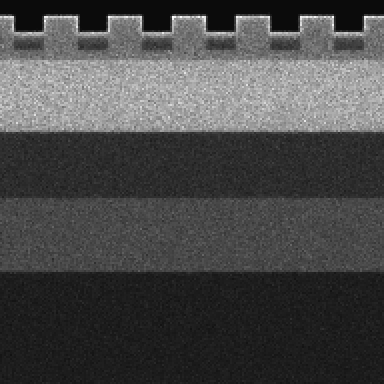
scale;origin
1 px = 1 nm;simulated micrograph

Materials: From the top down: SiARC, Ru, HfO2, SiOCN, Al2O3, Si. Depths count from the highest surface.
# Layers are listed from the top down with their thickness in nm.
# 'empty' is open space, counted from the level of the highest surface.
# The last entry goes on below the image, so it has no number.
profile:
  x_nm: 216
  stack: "empty 16, SiARC 18, Ru 10, HfO2 72, SiOCN 66, Al2O3 74, Si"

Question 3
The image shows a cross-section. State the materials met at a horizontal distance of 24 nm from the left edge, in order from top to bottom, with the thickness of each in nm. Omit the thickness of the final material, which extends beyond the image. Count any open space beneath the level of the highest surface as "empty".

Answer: empty 16, SiARC 18, Ru 10, HfO2 72, SiOCN 66, Al2O3 74, Si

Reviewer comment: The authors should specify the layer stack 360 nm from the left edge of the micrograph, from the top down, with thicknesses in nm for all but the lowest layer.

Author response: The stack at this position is empty 16, SiARC 18, Ru 10, HfO2 72, SiOCN 66, Al2O3 74, Si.